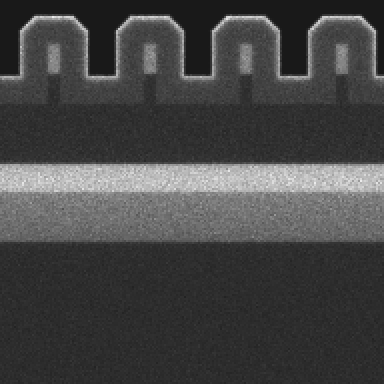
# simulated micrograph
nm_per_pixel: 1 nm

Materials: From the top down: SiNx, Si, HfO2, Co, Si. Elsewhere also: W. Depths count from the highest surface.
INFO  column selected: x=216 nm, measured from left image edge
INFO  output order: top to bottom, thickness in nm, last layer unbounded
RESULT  empty 10, SiNx 78, Si 60, HfO2 28, Co 50, Si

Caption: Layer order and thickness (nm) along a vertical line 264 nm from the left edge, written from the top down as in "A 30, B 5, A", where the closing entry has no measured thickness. SiNx 88, Si 60, HfO2 28, Co 50, Si